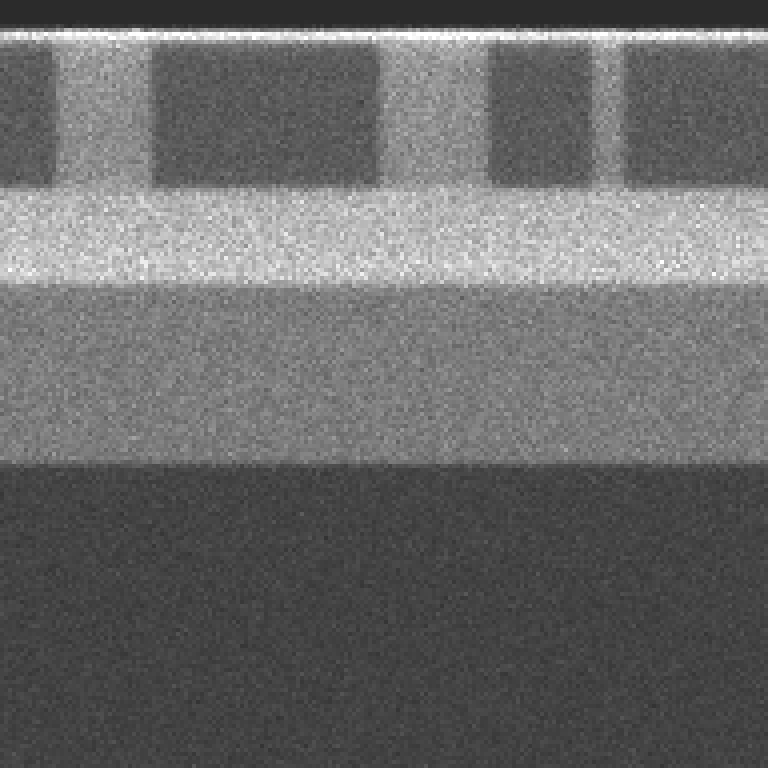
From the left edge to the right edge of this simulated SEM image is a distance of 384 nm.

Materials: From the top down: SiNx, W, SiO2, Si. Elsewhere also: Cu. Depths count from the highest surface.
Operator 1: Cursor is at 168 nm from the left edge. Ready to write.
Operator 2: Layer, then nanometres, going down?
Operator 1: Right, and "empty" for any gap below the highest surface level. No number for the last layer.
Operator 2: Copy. SiNx 78, W 48, SiO2 90, Si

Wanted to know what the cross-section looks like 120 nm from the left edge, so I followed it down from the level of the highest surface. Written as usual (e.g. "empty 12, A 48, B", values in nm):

SiNx 78, W 48, SiO2 90, Si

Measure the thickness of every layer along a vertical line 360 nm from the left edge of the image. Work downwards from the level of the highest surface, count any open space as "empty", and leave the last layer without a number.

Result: SiNx 78, W 48, SiO2 90, Si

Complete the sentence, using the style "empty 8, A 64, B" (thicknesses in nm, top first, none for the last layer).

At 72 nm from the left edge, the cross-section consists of Cu 78, W 48, SiO2 90, Si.